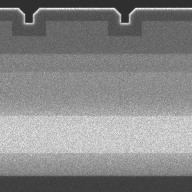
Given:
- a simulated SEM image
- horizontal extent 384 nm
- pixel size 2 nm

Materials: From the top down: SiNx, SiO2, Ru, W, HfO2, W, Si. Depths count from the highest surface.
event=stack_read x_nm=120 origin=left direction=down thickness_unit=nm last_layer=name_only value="SiNx 26, SiO2 66, Ru 36, W 88, HfO2 74, W 46, Si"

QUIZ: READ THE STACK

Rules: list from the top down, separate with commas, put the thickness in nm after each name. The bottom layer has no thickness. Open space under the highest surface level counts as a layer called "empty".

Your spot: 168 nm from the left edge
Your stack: SiNx 26, SiO2 66, Ru 36, W 88, HfO2 74, W 46, Si